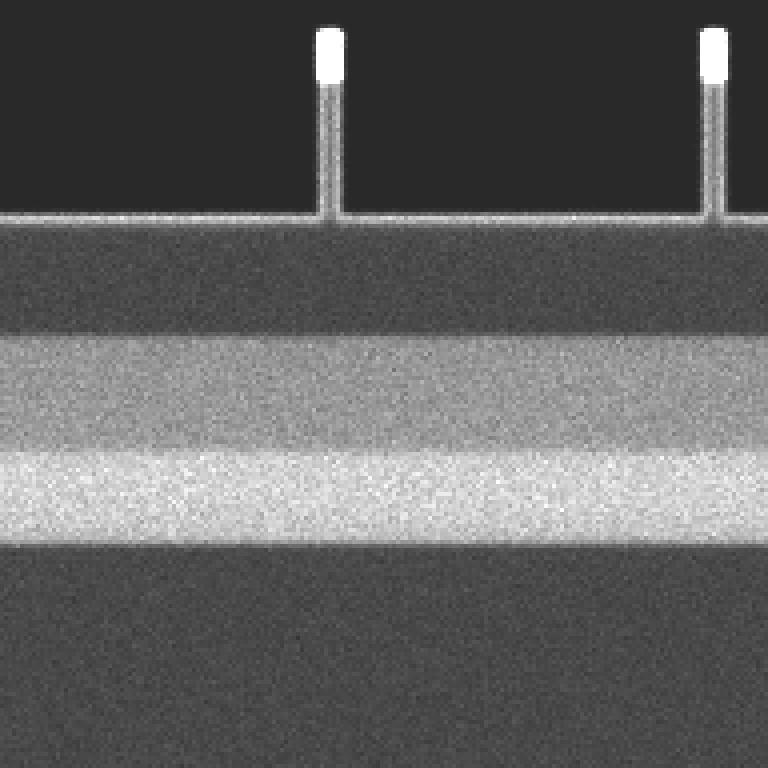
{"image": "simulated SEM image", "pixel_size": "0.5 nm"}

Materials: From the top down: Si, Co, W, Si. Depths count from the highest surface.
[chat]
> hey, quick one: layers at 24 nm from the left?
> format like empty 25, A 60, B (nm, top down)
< empty 92, Si 60, Co 58, W 46, Si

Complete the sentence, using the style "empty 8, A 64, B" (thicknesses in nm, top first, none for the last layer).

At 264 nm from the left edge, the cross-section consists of empty 92, Si 60, Co 58, W 46, Si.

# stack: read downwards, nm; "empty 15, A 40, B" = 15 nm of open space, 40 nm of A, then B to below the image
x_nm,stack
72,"empty 92, Si 60, Co 58, W 46, Si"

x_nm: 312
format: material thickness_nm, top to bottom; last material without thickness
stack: empty 92, Si 60, Co 58, W 46, Si